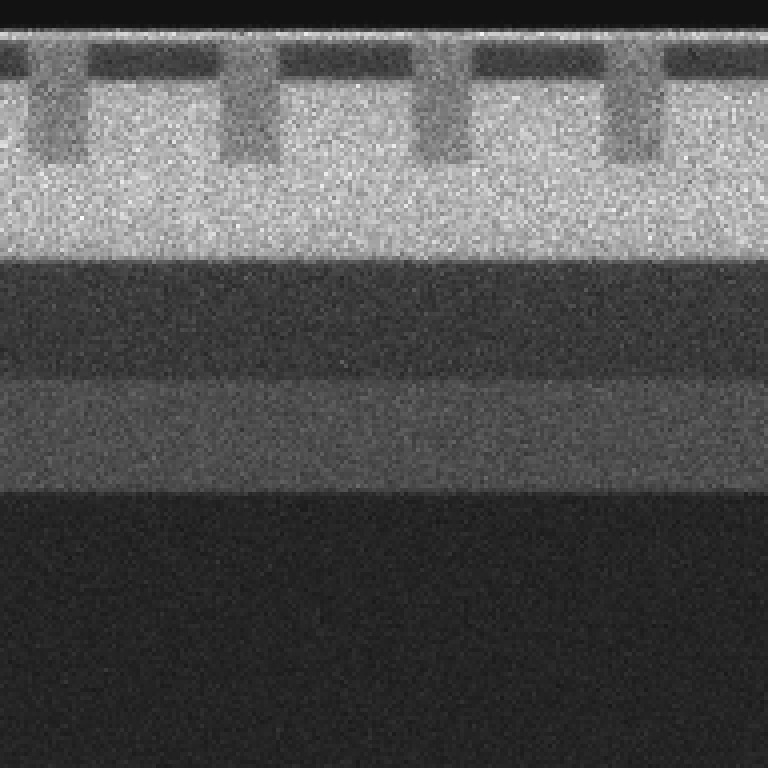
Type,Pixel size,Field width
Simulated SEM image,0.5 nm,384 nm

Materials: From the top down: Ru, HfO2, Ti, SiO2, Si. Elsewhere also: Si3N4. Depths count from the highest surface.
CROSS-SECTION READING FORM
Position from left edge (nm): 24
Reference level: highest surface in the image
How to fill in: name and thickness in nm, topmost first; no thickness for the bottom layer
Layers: Ru 66, HfO2 48, Ti 60, SiO2 56, Si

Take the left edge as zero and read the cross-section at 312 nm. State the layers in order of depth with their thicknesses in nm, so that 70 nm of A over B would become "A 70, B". Ru 66, HfO2 48, Ti 60, SiO2 56, Si